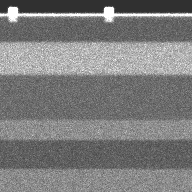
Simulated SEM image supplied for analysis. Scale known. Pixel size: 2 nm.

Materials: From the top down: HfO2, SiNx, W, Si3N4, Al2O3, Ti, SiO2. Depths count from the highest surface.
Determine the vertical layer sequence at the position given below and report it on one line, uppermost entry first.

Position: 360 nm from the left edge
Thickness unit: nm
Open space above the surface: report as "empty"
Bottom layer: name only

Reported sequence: empty 12, SiNx 56, W 66, Si3N4 90, Al2O3 40, Ti 58, SiO2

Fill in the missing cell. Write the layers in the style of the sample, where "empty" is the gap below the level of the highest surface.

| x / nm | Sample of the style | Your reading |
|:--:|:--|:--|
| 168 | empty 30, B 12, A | empty 12, SiNx 56, W 66, Si3N4 90, Al2O3 40, Ti 58, SiO2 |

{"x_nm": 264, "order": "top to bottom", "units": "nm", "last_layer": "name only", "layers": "empty 12, SiNx 56, W 66, Si3N4 90, Al2O3 40, Ti 58, SiO2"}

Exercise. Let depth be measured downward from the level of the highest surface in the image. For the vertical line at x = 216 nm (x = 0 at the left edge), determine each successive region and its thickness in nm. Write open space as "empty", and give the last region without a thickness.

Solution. HfO2 28, SiNx 40, W 66, Si3N4 90, Al2O3 40, Ti 58, SiO2